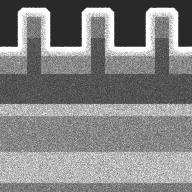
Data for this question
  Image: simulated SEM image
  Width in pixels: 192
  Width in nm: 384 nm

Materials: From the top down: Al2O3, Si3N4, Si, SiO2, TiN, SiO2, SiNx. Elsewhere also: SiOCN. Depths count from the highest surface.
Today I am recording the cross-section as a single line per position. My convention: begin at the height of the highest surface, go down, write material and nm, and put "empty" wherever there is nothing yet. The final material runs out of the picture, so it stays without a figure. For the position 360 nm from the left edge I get empty 78, Al2O3 18, Si3N4 36, Si 60, SiO2 24, TiN 72, SiO2 62, SiNx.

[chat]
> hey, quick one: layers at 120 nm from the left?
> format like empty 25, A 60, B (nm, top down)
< empty 78, Al2O3 18, Si3N4 36, Si 60, SiO2 24, TiN 72, SiO2 62, SiNx